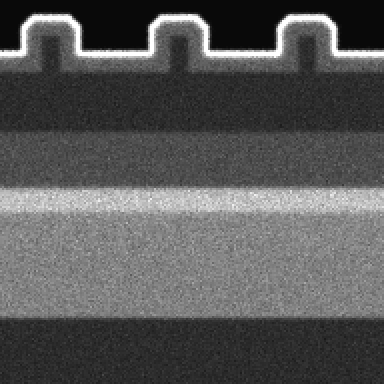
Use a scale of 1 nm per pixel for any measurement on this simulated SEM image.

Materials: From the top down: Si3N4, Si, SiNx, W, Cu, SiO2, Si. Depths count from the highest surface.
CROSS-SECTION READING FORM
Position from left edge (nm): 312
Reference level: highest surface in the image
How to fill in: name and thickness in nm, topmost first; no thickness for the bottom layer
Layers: Si3N4 20, Si 96, SiNx 56, W 24, Cu 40, SiO2 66, Si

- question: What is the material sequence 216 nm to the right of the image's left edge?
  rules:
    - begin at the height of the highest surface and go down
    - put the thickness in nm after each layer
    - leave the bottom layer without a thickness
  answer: empty 36, Si3N4 20, Si 60, SiNx 56, W 24, Cu 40, SiO2 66, Si